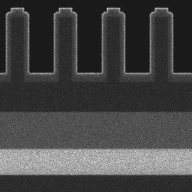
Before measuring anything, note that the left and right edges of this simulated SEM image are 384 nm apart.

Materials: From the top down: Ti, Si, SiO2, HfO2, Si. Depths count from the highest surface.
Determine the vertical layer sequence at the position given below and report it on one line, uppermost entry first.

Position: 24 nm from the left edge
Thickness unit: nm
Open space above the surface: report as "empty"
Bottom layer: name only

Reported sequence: Ti 18, Si 190, SiO2 74, HfO2 52, Si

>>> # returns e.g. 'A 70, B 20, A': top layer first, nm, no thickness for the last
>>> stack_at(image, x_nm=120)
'Ti 18, Si 190, SiO2 74, HfO2 52, Si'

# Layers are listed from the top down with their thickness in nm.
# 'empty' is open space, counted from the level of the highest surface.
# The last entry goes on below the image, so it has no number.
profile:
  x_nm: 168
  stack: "empty 130, Ti 18, Si 60, SiO2 74, HfO2 52, Si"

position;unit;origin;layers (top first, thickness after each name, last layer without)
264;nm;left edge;empty 130, Ti 18, Si 60, SiO2 74, HfO2 52, Si